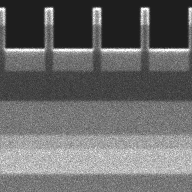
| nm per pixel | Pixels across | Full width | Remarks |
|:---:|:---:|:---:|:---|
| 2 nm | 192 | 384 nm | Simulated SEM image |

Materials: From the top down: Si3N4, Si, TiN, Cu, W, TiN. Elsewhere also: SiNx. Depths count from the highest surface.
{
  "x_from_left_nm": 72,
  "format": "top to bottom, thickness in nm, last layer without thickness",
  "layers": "empty 82, Si3N4 44, Si 60, TiN 68, Cu 28, W 50, TiN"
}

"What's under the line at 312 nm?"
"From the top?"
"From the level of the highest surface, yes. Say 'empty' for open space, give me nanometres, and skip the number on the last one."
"empty 82, Si3N4 44, Si 60, TiN 68, Cu 28, W 50, TiN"